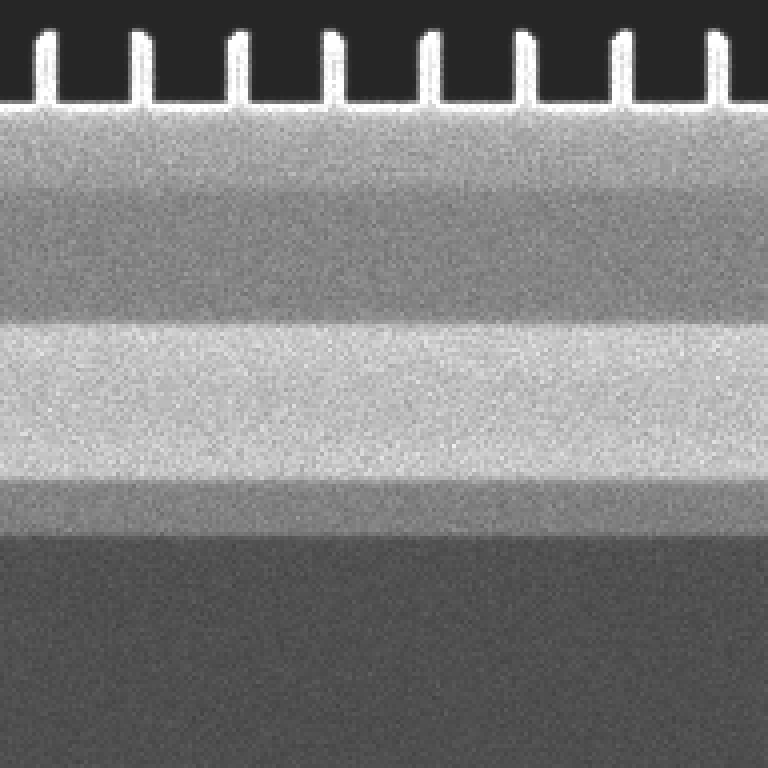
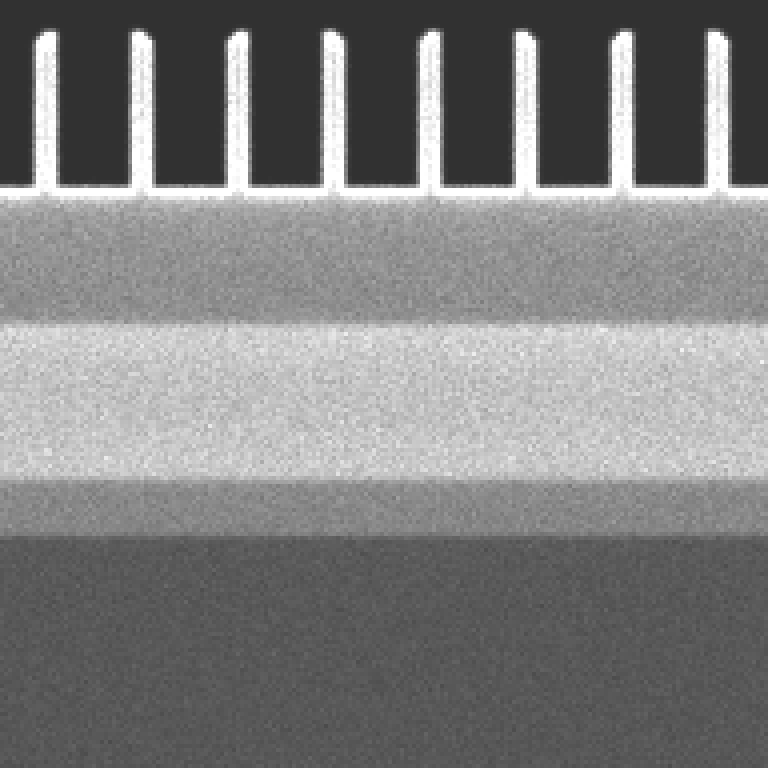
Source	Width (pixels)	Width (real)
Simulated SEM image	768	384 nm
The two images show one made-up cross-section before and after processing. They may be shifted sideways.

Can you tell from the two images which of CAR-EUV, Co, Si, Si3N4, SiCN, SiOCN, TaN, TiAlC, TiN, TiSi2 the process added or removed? Yes, it removed TiN.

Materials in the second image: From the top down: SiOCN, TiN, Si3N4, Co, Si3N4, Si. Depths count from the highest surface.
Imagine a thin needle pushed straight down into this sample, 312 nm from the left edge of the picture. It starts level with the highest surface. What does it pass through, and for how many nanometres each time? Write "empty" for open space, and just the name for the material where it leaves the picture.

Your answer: SiOCN 36, TiN 42, Si3N4 68, Co 78, Si3N4 28, Si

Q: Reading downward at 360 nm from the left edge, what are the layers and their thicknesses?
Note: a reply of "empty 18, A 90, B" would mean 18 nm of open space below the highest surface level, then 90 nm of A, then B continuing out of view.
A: empty 2, SiOCN 34, TiN 42, Si3N4 68, Co 78, Si3N4 28, Si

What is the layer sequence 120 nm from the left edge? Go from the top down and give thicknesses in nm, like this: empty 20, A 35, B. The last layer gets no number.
SiOCN 36, TiN 42, Si3N4 68, Co 78, Si3N4 28, Si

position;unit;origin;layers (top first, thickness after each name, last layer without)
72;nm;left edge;empty 2, SiOCN 34, TiN 42, Si3N4 68, Co 78, Si3N4 28, Si